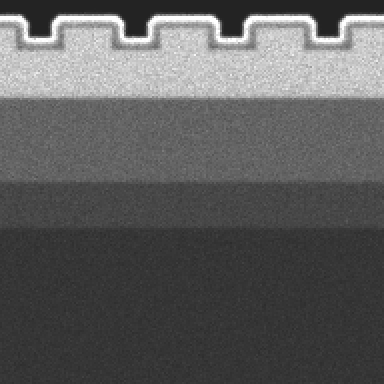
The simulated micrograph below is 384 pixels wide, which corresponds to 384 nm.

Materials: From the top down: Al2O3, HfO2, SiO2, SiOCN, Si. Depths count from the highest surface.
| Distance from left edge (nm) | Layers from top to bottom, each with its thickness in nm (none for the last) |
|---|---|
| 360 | Al2O3 12, HfO2 70, SiO2 84, SiOCN 46, Si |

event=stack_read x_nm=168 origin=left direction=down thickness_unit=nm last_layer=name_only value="Al2O3 12, HfO2 70, SiO2 84, SiOCN 46, Si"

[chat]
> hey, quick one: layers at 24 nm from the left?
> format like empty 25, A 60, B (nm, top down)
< empty 4, Al2O3 30, HfO2 48, SiO2 84, SiOCN 46, Si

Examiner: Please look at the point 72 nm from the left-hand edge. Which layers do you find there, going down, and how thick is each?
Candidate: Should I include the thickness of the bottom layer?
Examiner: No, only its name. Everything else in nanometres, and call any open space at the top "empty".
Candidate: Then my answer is Al2O3 12, HfO2 70, SiO2 84, SiOCN 46, Si